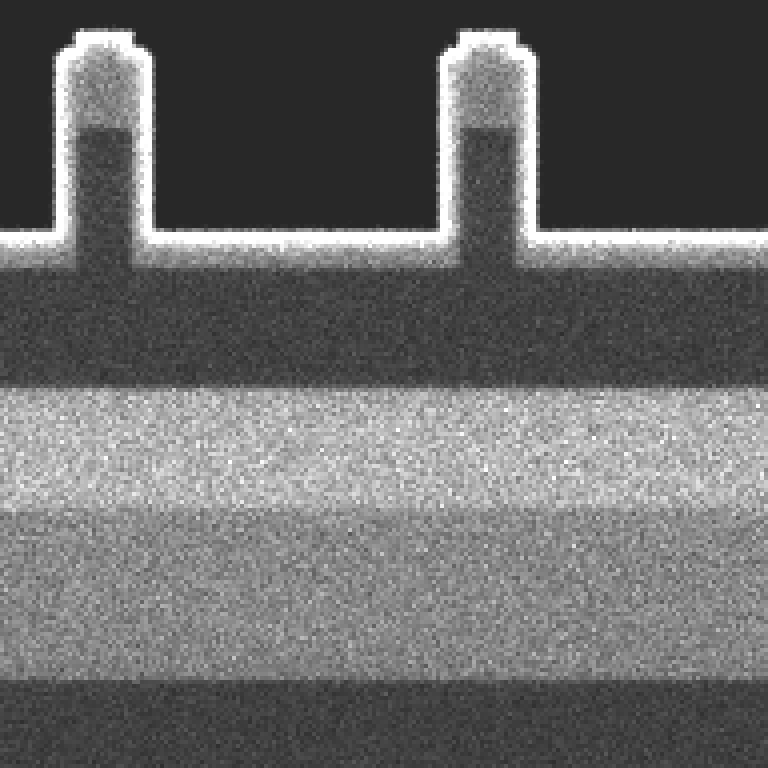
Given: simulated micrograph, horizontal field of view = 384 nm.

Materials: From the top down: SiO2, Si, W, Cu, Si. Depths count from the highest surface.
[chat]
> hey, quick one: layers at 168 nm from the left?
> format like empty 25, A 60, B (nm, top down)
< empty 100, SiO2 18, Si 60, W 60, Cu 86, Si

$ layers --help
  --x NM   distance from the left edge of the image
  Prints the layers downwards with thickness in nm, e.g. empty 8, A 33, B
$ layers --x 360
empty 100, SiO2 18, Si 60, W 60, Cu 86, Si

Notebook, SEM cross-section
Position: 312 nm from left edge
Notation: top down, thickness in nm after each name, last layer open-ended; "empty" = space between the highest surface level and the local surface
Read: empty 100, SiO2 18, Si 60, W 60, Cu 86, Si